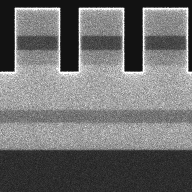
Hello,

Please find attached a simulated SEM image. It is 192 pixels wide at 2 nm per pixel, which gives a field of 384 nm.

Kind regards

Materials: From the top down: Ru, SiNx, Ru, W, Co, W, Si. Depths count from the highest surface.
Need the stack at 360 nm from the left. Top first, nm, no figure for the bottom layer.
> Ru 56, SiNx 28, Ru 30, W 90, Co 26, W 54, Si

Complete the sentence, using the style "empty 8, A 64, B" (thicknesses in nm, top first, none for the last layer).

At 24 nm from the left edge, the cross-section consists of empty 128, W 76, Co 26, W 54, Si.